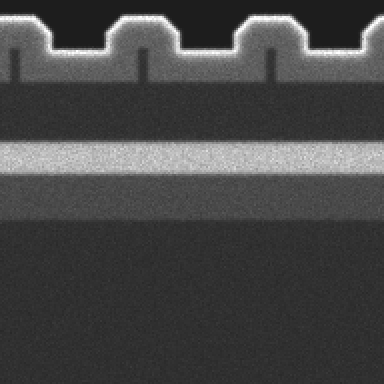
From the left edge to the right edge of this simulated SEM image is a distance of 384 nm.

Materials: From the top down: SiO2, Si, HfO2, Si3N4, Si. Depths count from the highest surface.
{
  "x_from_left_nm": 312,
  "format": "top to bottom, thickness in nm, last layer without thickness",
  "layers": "empty 34, SiO2 32, Si 60, HfO2 32, Si3N4 46, Si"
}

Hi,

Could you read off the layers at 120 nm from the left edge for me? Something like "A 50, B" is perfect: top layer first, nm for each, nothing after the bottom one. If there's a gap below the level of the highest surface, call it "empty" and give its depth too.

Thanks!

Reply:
empty 2, SiO2 64, Si 60, HfO2 32, Si3N4 46, Si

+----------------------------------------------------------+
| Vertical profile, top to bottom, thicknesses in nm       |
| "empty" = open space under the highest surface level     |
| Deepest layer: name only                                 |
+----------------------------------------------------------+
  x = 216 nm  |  empty 34, SiO2 32, Si 60, HfO2 32, Si3N4 46, Si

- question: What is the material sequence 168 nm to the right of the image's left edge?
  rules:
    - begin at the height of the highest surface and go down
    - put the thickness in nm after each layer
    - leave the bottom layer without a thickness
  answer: empty 6, SiO2 60, Si 60, HfO2 32, Si3N4 46, Si